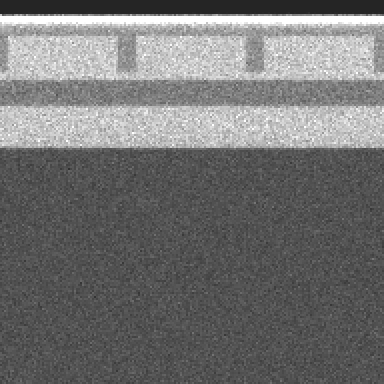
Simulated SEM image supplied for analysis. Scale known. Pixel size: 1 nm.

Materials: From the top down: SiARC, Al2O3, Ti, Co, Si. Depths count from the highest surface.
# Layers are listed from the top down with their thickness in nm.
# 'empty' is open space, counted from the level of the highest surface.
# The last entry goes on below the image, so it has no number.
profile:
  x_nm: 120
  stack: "SiARC 56, Al2O3 8, Ti 26, Co 42, Si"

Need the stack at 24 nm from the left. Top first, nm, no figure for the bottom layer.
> SiARC 20, Al2O3 44, Ti 26, Co 42, Si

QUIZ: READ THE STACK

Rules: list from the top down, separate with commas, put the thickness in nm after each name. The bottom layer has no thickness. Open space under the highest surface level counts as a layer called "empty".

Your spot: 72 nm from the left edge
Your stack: SiARC 20, Al2O3 44, Ti 26, Co 42, Si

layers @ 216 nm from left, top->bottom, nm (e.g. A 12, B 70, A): SiARC 20, Al2O3 44, Ti 26, Co 42, Si